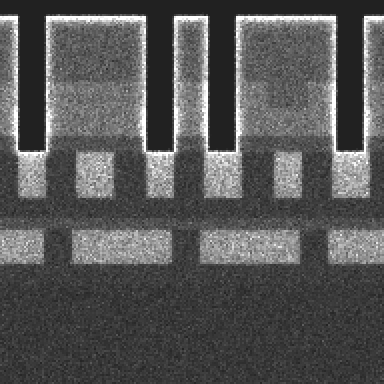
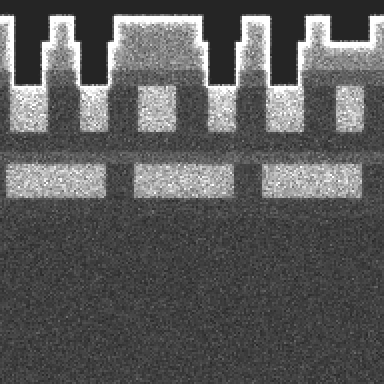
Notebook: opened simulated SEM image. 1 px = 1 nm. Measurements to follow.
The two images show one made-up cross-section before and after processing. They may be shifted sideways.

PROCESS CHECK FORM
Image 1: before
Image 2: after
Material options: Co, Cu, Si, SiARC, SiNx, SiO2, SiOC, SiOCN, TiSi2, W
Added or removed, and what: removed, SiARC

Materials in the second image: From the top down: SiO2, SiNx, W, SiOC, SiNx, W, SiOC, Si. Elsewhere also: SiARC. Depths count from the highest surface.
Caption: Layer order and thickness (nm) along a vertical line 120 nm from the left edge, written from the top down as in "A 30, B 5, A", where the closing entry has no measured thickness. SiO2 54, SiNx 16, SiOC 66, SiNx 12, SiOC 54, Si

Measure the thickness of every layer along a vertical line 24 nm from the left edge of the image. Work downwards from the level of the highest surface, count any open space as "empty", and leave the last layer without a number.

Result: empty 70, W 46, SiOC 20, SiNx 12, W 34, SiOC 20, Si